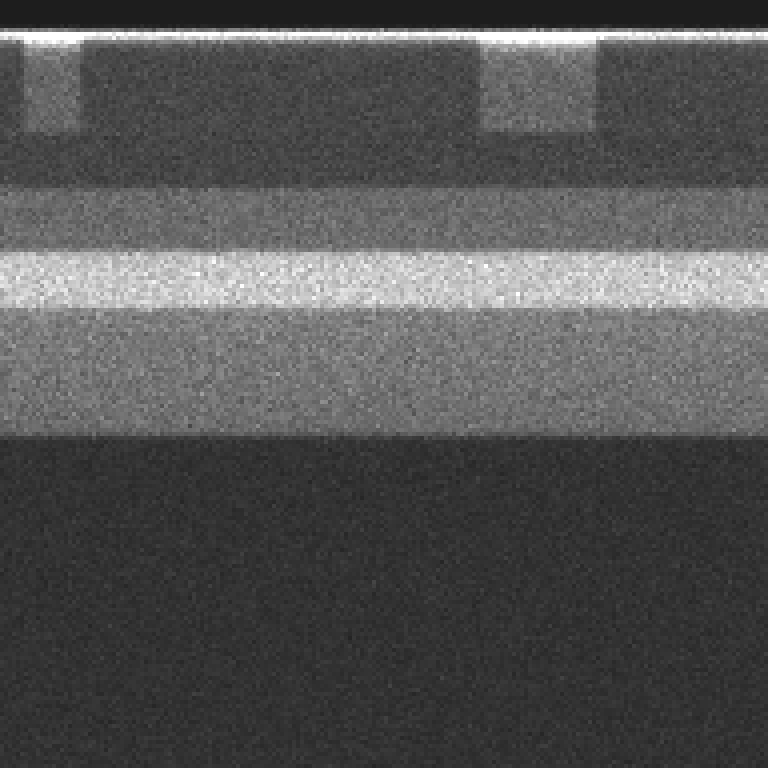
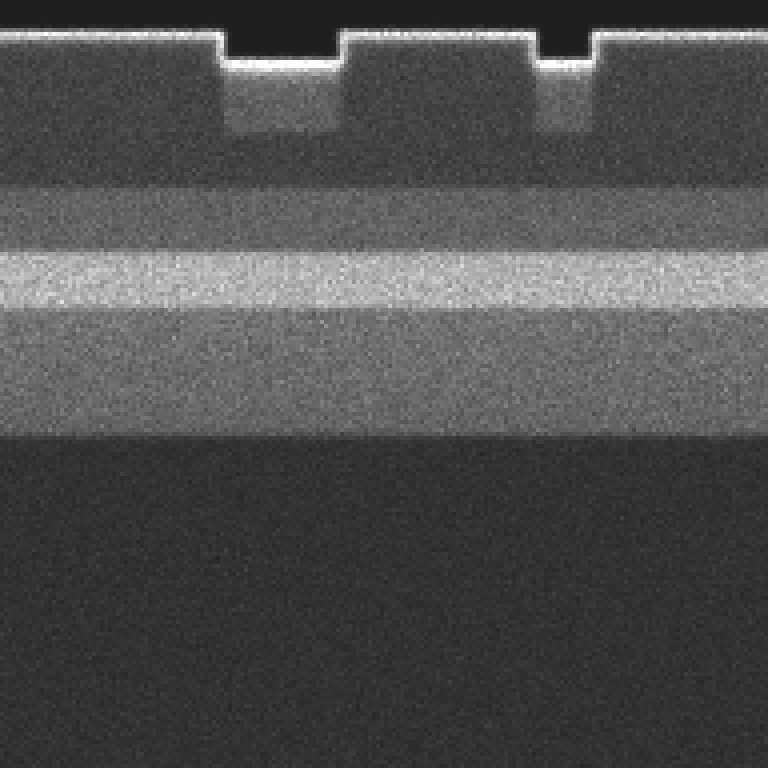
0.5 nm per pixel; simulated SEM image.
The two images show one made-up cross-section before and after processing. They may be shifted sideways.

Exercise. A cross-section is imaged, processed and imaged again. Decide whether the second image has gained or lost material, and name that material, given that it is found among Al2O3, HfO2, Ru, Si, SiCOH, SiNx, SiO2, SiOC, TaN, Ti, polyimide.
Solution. removed: SiO2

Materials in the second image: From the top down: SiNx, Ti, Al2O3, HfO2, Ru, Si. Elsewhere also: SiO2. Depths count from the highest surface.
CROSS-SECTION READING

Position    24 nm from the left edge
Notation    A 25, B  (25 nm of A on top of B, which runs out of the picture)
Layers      SiNx 50, Ti 28, Al2O3 32, HfO2 28, Ru 64, Si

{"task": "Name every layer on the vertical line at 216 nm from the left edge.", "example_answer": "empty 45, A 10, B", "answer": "SiNx 50, Ti 28, Al2O3 32, HfO2 28, Ru 64, Si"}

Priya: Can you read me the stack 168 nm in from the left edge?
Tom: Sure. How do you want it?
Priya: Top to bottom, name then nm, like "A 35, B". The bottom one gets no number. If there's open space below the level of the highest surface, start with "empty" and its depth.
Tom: empty 14, SiO2 36, Ti 28, Al2O3 32, HfO2 28, Ru 64, Si